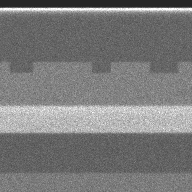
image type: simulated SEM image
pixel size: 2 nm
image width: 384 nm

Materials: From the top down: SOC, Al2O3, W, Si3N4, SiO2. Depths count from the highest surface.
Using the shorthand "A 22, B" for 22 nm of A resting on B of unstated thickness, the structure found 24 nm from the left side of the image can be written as SOC 130, Al2O3 66, W 54, Si3N4 80, SiO2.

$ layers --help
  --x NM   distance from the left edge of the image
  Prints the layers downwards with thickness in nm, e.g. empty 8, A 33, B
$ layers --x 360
SOC 108, Al2O3 88, W 54, Si3N4 80, SiO2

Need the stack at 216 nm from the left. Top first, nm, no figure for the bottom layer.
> SOC 130, Al2O3 66, W 54, Si3N4 80, SiO2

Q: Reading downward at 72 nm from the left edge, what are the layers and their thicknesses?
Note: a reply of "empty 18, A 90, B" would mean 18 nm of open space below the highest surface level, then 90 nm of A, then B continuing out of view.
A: SOC 108, Al2O3 88, W 54, Si3N4 80, SiO2